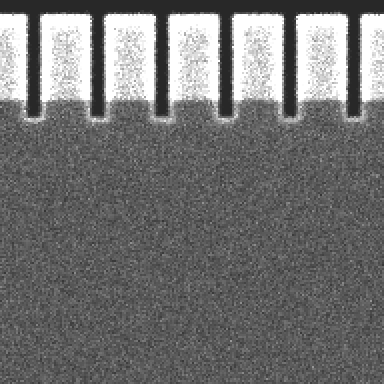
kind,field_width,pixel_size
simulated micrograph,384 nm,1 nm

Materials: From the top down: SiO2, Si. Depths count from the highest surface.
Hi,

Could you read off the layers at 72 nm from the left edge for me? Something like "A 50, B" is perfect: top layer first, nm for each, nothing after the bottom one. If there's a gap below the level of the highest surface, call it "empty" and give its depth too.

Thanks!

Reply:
SiO2 84, Si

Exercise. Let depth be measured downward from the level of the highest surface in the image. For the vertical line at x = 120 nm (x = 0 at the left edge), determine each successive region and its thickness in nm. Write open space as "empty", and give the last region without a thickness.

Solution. SiO2 84, Si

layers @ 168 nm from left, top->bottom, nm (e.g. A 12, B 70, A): empty 102, Si